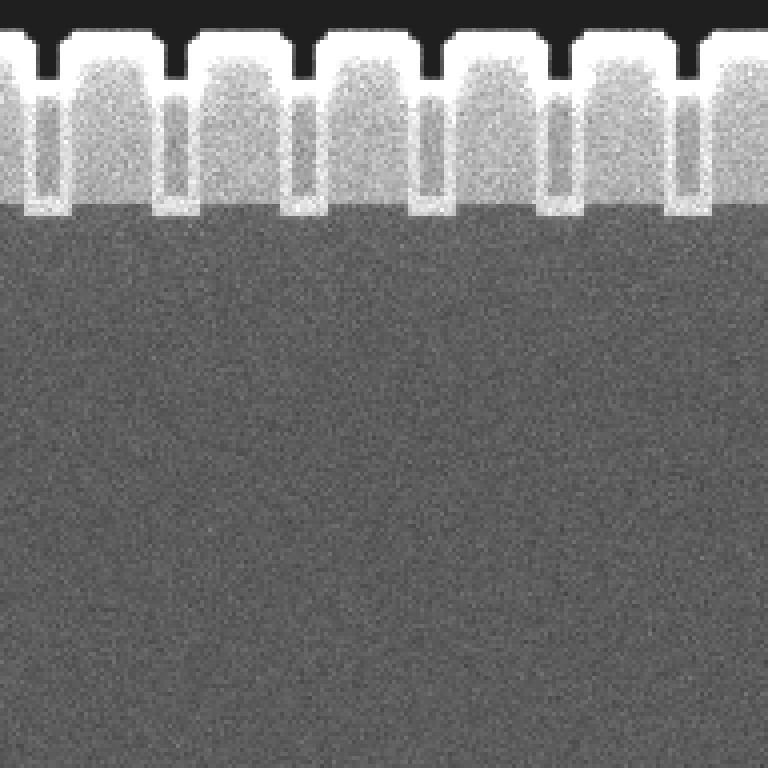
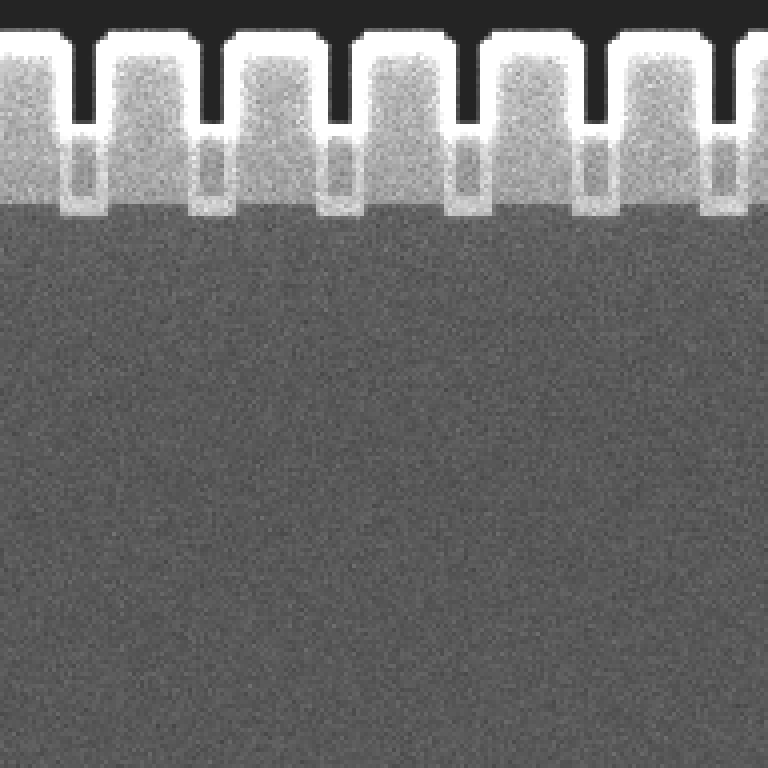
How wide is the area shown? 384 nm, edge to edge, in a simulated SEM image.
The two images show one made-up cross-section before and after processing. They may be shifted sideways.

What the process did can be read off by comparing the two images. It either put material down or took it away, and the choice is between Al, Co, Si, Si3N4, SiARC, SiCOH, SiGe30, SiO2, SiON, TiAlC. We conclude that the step removed SiARC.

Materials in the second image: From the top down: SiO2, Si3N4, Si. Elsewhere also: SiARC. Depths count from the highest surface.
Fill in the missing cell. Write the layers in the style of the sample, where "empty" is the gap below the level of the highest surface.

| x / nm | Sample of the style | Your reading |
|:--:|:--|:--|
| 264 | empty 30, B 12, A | SiO2 10, Si3N4 76, Si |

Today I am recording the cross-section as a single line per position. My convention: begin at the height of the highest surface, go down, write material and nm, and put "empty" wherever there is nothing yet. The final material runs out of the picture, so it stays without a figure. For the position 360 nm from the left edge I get empty 46, SiARC 36, SiO2 10, Si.